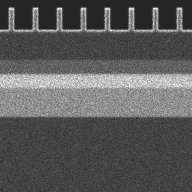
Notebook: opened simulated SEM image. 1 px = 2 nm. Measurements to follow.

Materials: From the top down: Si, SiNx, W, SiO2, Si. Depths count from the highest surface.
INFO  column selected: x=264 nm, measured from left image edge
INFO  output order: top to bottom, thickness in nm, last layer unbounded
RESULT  Si 104, SiNx 28, W 28, SiO2 58, Si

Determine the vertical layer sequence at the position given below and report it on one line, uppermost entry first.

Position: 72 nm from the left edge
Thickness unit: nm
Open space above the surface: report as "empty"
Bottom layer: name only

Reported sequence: Si 104, SiNx 28, W 28, SiO2 58, Si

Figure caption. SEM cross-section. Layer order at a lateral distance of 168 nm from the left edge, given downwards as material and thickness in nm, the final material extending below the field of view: Si 104, SiNx 28, W 28, SiO2 58, Si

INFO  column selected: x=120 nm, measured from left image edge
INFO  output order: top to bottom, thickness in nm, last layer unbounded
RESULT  Si 104, SiNx 28, W 28, SiO2 58, Si